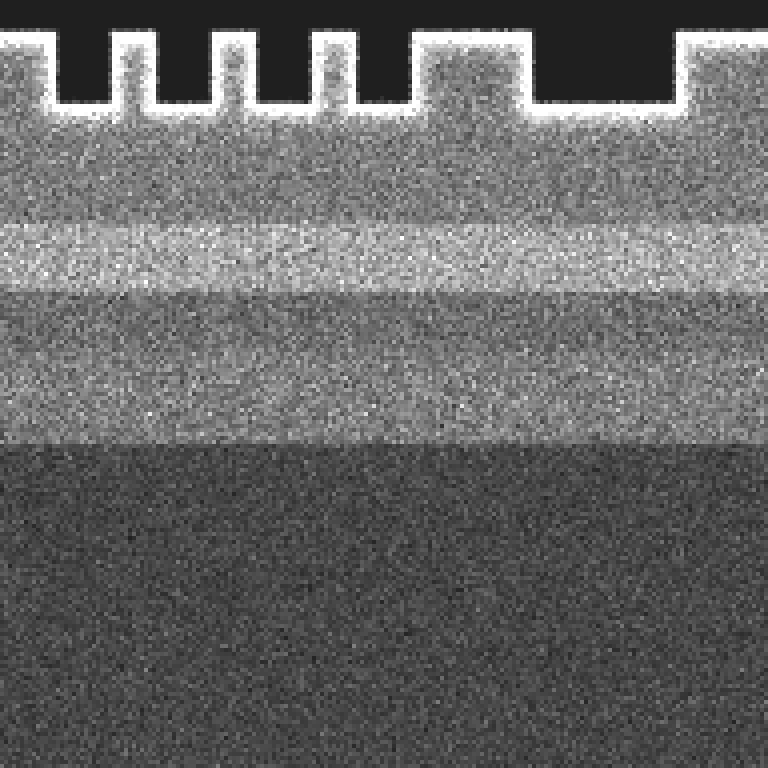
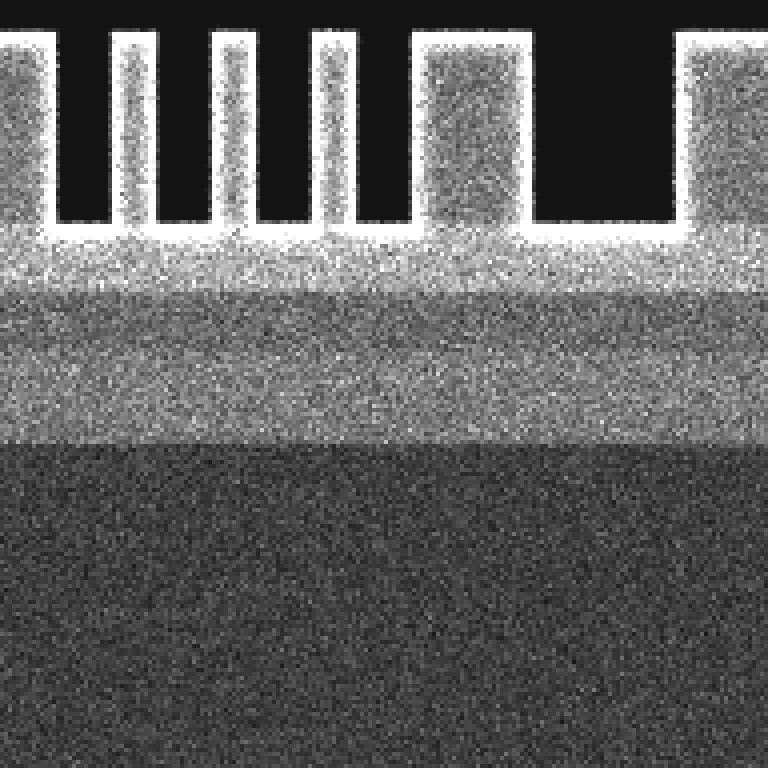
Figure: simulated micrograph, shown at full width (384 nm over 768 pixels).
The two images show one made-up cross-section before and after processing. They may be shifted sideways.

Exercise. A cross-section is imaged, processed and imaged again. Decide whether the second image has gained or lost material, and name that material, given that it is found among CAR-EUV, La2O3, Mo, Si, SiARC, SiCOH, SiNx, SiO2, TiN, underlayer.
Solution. removed: underlayer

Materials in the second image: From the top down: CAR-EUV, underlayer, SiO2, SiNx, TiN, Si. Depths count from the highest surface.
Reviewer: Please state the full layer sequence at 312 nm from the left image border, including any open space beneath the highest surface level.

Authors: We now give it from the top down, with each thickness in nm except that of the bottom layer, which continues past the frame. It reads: empty 96, SiO2 34, SiNx 30, TiN 46, Si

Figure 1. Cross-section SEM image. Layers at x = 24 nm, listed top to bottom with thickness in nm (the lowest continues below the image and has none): CAR-EUV 36, underlayer 60, SiO2 34, SiNx 30, TiN 46, Si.